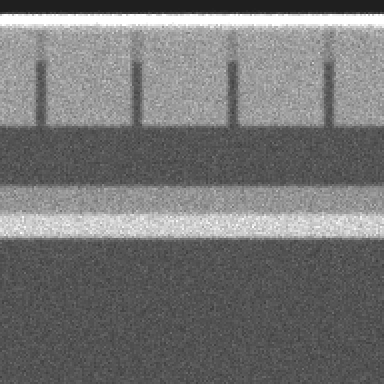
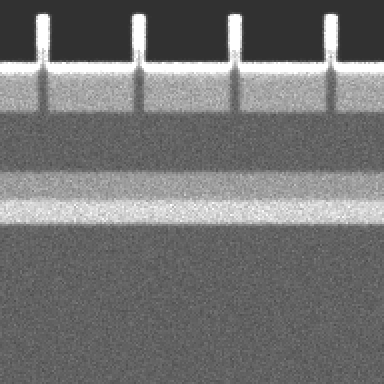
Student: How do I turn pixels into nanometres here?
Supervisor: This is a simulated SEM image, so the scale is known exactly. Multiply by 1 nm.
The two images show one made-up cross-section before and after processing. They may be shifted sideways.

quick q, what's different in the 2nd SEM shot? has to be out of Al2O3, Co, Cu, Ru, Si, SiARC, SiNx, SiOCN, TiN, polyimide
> SiARC removed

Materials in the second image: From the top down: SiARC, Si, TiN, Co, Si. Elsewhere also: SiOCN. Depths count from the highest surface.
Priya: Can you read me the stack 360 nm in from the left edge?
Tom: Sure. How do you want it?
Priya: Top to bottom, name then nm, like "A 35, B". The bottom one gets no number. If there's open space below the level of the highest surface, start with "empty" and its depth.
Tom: empty 48, SiARC 48, Si 60, TiN 28, Co 24, Si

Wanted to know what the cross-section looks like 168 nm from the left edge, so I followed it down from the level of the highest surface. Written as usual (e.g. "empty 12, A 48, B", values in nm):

empty 48, SiARC 48, Si 60, TiN 28, Co 24, Si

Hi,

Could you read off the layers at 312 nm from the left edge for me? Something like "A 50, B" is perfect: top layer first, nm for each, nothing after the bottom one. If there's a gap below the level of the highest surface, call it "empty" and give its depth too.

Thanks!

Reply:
empty 48, SiARC 48, Si 60, TiN 28, Co 24, Si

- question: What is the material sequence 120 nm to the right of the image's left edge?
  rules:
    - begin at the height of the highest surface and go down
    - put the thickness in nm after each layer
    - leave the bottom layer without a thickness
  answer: empty 48, SiARC 48, Si 60, TiN 28, Co 24, Si